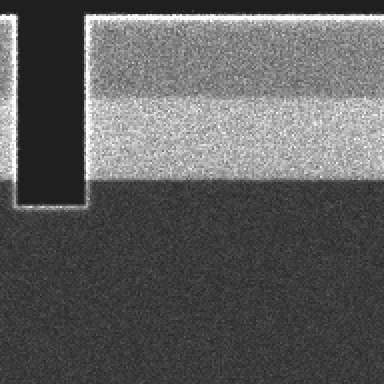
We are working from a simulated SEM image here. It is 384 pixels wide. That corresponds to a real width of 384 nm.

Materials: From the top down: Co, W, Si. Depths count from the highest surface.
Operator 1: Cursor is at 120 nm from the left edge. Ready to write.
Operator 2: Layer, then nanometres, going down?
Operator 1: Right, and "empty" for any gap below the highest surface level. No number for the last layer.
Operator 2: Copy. Co 82, W 82, Si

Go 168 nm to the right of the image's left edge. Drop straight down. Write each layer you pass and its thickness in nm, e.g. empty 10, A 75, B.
Co 82, W 82, Si